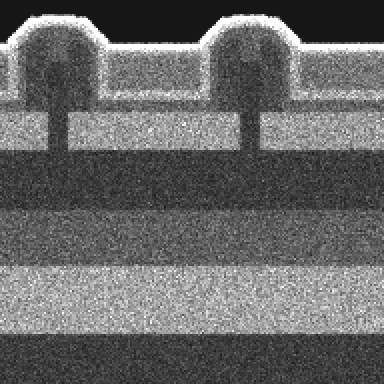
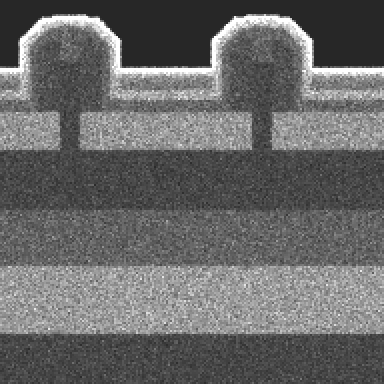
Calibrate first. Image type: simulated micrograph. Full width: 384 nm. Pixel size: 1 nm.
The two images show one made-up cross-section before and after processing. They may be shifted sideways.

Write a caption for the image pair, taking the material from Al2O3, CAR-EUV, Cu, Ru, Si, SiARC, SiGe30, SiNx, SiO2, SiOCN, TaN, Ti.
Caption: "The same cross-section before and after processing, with SiARC removed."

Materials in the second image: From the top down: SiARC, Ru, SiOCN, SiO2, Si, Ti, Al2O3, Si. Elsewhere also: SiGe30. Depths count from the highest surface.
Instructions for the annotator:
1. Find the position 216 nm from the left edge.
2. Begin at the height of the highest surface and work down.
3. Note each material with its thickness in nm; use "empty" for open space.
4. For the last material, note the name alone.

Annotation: empty 20, Ru 64, SiOCN 12, SiO2 38, Si 60, Ti 56, Al2O3 68, Si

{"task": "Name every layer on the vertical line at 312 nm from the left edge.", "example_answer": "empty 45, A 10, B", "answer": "empty 52, SiARC 22, Ru 10, SiOCN 12, SiO2 38, Si 60, Ti 56, Al2O3 68, Si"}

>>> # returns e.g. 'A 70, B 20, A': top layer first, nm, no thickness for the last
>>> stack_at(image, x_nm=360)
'empty 52, SiARC 22, Ru 10, SiOCN 12, SiO2 38, Si 60, Ti 56, Al2O3 68, Si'